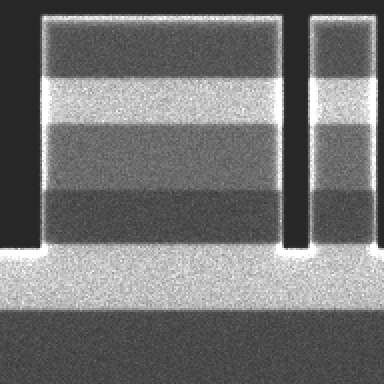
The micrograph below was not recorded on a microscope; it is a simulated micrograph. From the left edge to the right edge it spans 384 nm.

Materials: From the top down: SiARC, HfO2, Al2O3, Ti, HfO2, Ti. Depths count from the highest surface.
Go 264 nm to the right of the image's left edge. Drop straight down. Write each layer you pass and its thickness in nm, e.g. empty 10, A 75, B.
SiARC 62, HfO2 46, Al2O3 66, Ti 54, HfO2 66, Ti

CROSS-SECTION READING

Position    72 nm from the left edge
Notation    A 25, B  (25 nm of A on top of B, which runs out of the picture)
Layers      SiARC 62, HfO2 46, Al2O3 66, Ti 54, HfO2 66, Ti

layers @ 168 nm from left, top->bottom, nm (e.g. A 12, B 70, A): SiARC 62, HfO2 46, Al2O3 66, Ti 54, HfO2 66, Ti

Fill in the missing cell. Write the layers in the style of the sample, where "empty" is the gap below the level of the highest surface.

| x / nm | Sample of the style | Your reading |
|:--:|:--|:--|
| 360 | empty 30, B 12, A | SiARC 62, HfO2 46, Al2O3 66, Ti 54, HfO2 66, Ti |